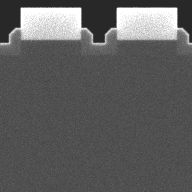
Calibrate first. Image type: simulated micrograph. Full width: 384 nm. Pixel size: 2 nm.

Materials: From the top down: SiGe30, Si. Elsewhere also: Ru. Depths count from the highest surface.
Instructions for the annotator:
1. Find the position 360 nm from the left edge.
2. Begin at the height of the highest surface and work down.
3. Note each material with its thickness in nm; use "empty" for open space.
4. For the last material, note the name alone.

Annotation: empty 40, SiGe30 54, Si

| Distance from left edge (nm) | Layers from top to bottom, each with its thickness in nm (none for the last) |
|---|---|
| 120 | Ru 64, Si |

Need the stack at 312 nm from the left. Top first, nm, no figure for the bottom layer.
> Ru 64, Si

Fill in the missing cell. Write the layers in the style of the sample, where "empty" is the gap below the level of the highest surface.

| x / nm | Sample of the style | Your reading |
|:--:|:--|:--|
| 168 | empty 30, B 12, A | empty 40, SiGe30 54, Si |